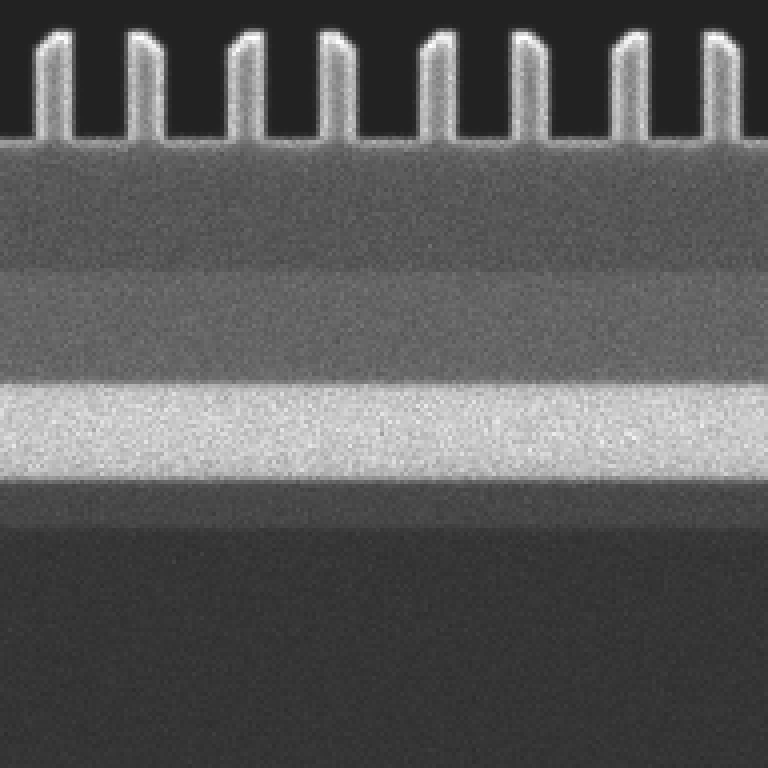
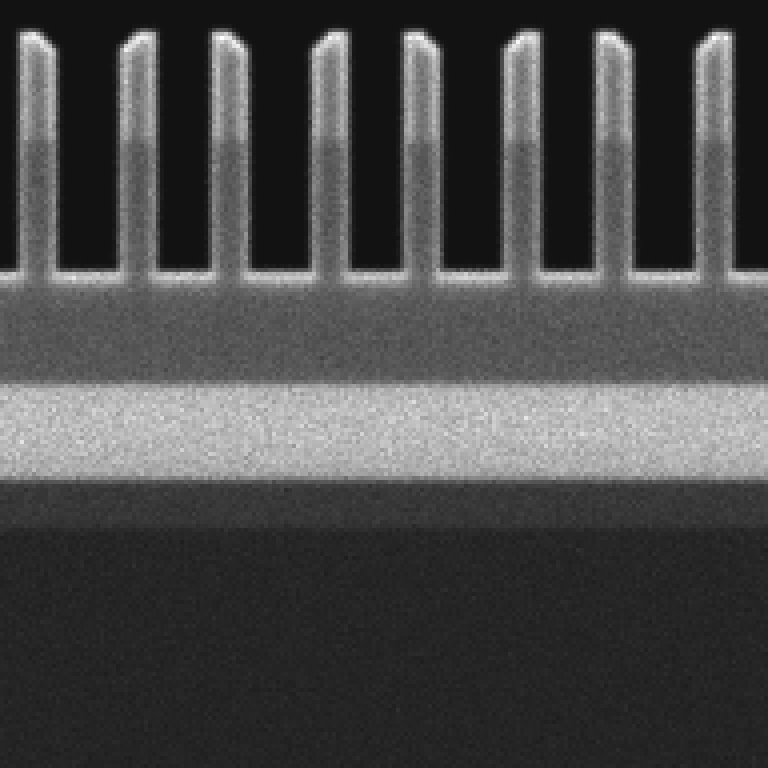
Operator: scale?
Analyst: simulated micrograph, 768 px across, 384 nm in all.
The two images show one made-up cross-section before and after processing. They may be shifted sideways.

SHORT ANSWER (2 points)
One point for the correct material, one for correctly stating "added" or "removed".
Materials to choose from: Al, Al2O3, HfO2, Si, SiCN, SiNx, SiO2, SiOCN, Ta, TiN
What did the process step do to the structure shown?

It removed TiN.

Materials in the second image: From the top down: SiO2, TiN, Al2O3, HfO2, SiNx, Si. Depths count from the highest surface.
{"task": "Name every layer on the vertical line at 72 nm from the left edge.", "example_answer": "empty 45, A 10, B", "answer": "SiO2 54, TiN 66, Al2O3 56, HfO2 48, SiNx 24, Si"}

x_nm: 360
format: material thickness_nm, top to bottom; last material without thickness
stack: SiO2 54, TiN 66, Al2O3 56, HfO2 48, SiNx 24, Si